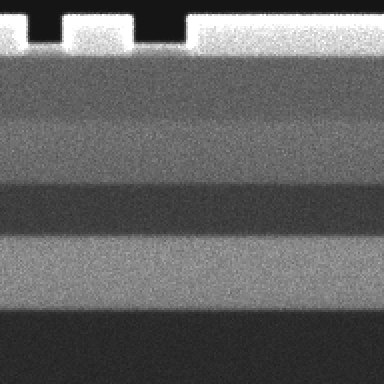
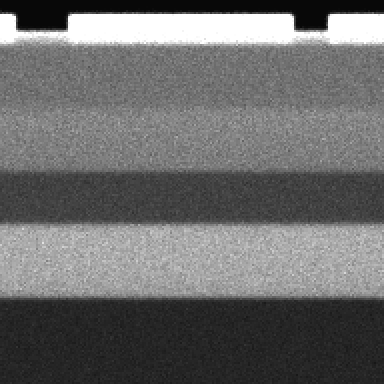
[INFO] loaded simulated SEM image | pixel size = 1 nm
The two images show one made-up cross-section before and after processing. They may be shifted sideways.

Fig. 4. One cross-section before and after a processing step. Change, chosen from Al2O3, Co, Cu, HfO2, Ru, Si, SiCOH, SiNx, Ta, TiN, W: HfO2 removed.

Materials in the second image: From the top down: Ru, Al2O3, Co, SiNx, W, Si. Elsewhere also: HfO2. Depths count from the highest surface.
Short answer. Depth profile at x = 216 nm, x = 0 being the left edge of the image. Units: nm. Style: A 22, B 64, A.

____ HfO2 28, Al2O3 64, Co 64, SiNx 52, W 74, Si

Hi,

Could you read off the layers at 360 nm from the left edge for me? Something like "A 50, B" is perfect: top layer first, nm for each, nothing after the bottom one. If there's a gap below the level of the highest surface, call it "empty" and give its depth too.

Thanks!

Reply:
HfO2 28, Al2O3 64, Co 64, SiNx 52, W 74, Si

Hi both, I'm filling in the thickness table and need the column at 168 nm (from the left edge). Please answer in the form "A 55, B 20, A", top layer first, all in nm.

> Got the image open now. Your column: HfO2 28, Al2O3 64, Co 64, SiNx 52, W 74, Si